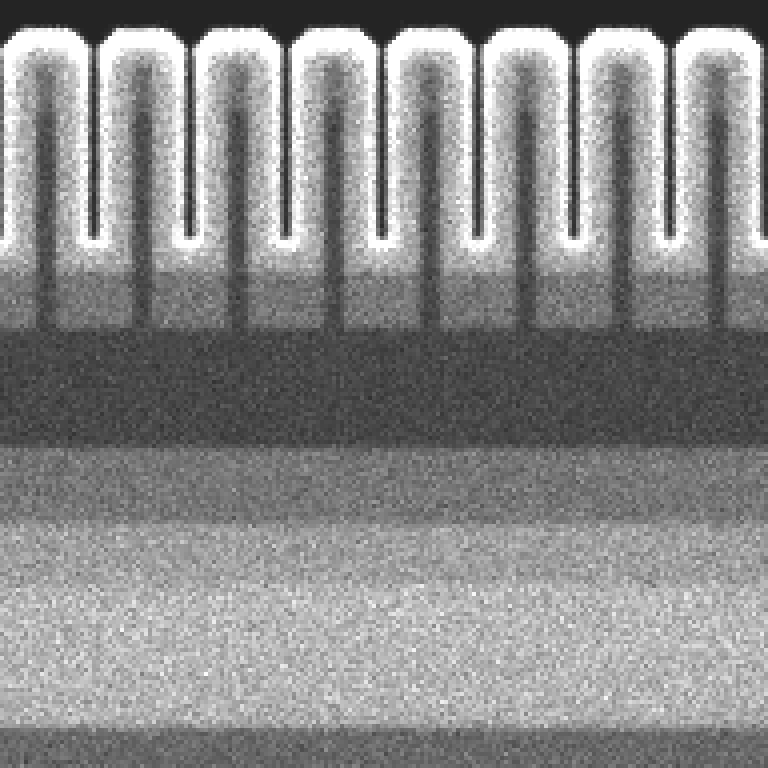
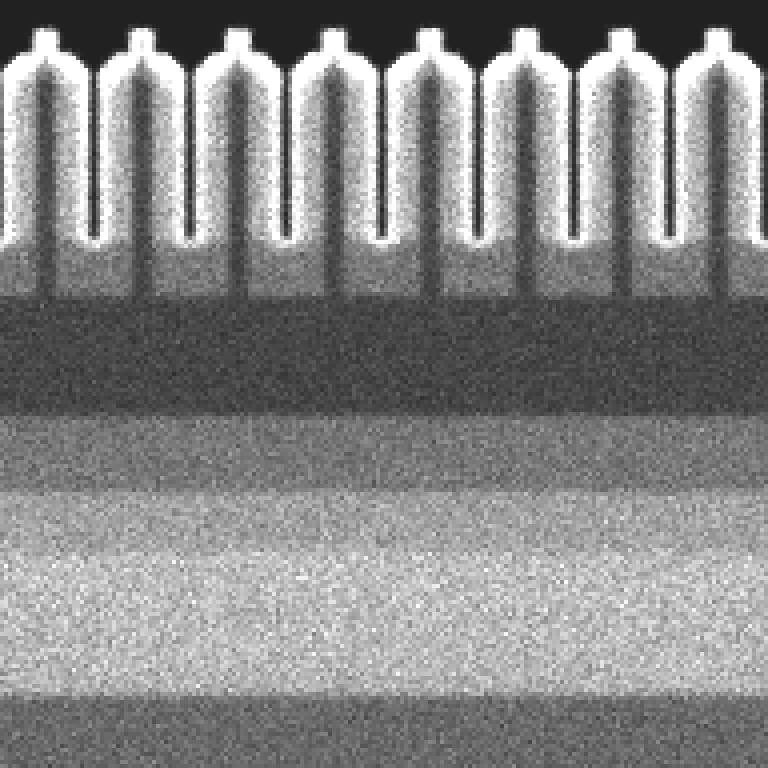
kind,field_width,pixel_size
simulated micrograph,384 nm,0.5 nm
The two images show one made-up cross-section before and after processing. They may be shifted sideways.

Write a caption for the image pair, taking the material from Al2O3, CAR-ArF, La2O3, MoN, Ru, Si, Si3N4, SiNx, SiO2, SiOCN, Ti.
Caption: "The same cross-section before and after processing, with Al2O3 removed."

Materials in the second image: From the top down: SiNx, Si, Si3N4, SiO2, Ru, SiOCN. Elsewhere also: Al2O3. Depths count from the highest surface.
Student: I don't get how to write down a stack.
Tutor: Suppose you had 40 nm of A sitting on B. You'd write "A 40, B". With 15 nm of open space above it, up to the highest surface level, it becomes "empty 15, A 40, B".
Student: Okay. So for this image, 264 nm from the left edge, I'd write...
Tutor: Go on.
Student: SiNx 24, Si 168, Si3N4 38, SiO2 30, Ru 72, SiOCN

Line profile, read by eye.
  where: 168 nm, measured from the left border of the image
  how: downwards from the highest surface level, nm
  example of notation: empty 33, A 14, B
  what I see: SiNx 24, Si 168, Si3N4 38, SiO2 30, Ru 72, SiOCN